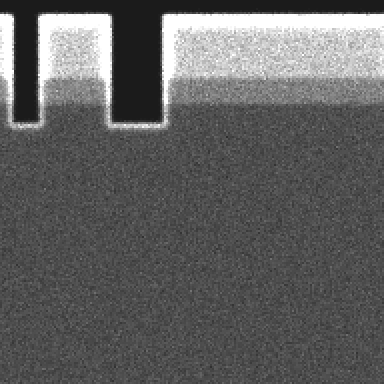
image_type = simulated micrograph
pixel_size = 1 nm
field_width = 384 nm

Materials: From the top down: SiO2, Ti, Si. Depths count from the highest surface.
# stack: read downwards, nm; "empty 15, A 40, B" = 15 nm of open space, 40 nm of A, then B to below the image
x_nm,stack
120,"empty 108, Si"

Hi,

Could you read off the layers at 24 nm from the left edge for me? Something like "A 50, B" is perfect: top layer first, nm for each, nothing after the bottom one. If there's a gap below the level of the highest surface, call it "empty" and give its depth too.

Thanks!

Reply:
empty 108, Si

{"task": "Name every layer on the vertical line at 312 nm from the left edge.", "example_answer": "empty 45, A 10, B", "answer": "SiO2 62, Ti 26, Si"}